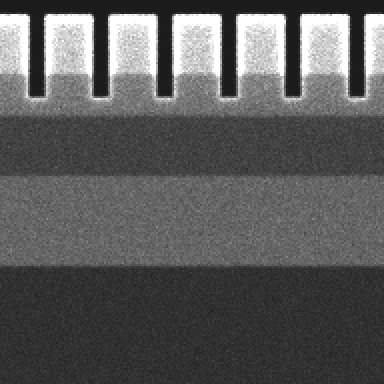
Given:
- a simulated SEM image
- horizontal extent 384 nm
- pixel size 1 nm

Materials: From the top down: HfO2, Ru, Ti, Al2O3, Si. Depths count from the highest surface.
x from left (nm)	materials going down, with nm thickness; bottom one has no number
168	empty 82, Ru 18, Ti 60, Al2O3 90, Si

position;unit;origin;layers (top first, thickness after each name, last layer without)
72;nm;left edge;HfO2 58, Ru 42, Ti 60, Al2O3 90, Si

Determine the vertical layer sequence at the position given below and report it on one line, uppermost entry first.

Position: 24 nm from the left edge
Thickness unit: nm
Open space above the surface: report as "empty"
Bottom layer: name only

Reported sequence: HfO2 58, Ru 42, Ti 60, Al2O3 90, Si